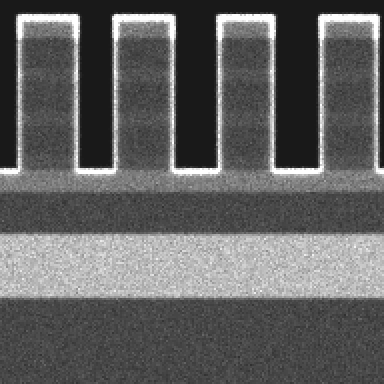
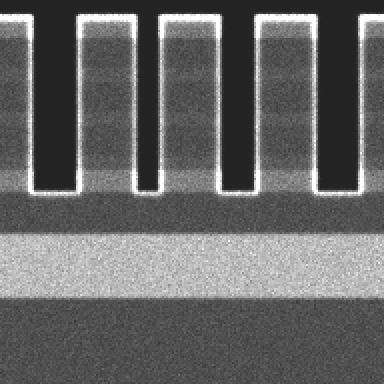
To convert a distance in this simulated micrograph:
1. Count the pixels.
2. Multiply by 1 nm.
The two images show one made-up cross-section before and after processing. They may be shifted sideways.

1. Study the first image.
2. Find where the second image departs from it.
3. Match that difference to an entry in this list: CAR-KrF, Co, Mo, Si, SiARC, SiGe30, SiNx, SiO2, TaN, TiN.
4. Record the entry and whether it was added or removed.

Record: TiN / removed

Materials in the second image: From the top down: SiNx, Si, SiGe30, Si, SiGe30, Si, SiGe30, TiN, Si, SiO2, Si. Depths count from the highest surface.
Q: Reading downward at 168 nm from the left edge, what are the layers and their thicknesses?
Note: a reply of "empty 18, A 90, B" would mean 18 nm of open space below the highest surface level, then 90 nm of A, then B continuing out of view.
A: SiNx 22, Si 30, SiGe30 14, Si 30, SiGe30 14, Si 30, SiGe30 14, TiN 22, Si 42, SiO2 64, Si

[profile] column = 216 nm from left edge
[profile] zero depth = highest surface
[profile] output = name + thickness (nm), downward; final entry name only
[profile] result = SiNx 22, Si 30, SiGe30 14, Si 30, SiGe30 14, Si 30, SiGe30 14, TiN 22, Si 42, SiO2 64, Si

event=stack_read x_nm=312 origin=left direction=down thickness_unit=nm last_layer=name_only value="SiNx 22, Si 30, SiGe30 14, Si 30, SiGe30 14, Si 30, SiGe30 14, TiN 22, Si 42, SiO2 64, Si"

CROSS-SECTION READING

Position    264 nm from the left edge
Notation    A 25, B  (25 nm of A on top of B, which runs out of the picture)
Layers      SiNx 22, Si 30, SiGe30 14, Si 30, SiGe30 14, Si 30, SiGe30 14, TiN 22, Si 42, SiO2 64, Si